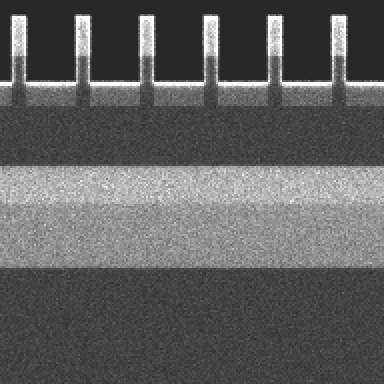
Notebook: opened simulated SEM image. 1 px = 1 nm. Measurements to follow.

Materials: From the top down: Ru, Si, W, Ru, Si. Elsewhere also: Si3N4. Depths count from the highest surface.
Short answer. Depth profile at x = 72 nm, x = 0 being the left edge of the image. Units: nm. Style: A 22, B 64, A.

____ empty 66, Si3N4 24, Si 60, W 38, Ru 64, Si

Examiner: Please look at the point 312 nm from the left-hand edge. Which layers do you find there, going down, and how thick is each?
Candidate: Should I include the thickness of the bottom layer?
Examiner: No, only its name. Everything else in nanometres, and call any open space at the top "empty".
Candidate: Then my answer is empty 66, Si3N4 24, Si 60, W 38, Ru 64, Si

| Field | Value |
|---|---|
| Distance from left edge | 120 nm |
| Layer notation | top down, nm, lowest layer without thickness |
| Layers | empty 66, Si3N4 24, Si 60, W 38, Ru 64, Si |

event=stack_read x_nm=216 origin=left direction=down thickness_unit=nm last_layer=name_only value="Ru 40, Si 110, W 38, Ru 64, Si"